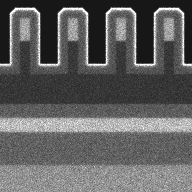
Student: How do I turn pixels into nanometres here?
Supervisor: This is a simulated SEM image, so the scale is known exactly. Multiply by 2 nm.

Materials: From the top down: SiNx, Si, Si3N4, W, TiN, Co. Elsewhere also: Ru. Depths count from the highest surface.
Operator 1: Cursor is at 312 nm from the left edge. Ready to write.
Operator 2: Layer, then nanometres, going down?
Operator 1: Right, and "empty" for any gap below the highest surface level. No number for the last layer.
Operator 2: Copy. empty 6, SiNx 126, Si 60, Si3N4 28, W 28, TiN 66, Co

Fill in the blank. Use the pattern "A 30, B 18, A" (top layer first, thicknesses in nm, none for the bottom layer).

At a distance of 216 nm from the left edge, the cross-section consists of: empty 6, SiNx 126, Si 60, Si3N4 28, W 28, TiN 66, Co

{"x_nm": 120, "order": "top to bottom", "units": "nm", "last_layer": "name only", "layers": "empty 6, SiNx 126, Si 60, Si3N4 28, W 28, TiN 66, Co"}